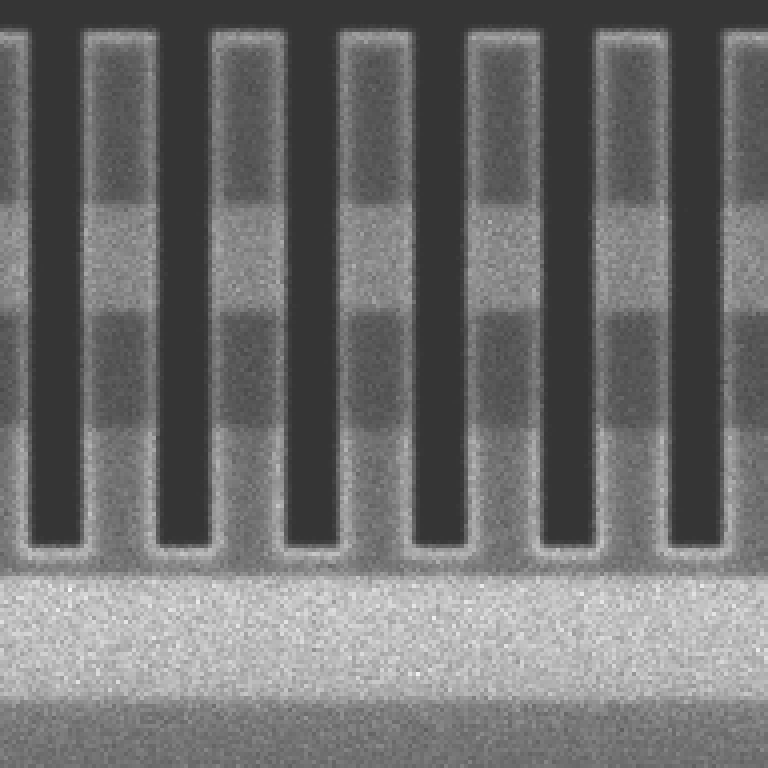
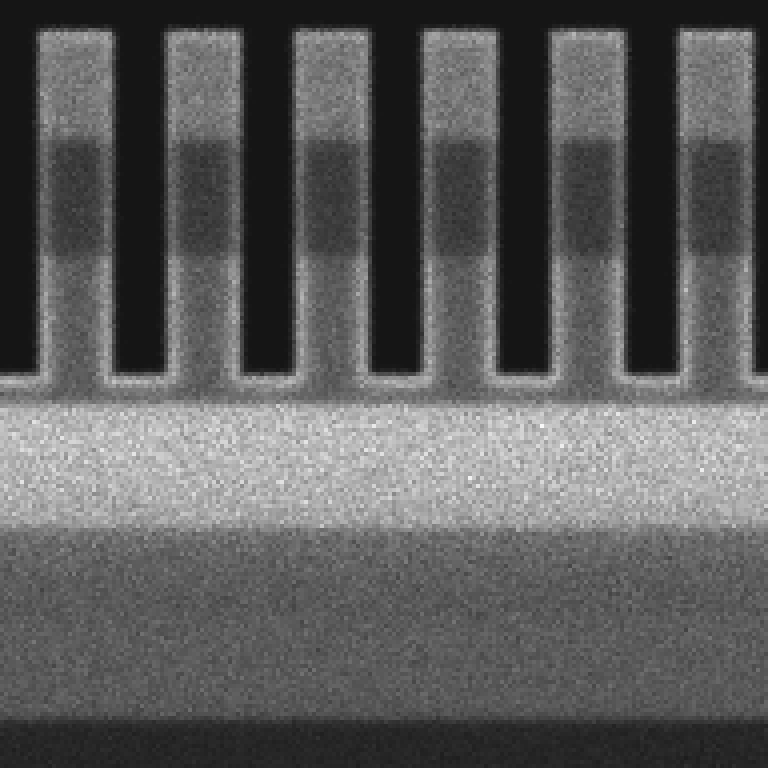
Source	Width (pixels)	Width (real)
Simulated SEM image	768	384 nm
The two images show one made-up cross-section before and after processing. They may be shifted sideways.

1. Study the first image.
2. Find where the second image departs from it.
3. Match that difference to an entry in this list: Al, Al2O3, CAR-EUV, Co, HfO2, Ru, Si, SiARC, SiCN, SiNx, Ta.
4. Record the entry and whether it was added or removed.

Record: SiARC / removed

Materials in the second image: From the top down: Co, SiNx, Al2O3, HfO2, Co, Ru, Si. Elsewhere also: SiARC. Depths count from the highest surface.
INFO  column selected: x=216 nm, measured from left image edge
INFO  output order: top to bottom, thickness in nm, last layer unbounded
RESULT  Co 54, SiNx 58, Al2O3 74, HfO2 62, Co 46, Ru 50, Si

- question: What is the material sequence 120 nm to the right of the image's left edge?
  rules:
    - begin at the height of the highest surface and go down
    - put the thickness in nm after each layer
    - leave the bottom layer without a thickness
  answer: empty 172, Al2O3 14, HfO2 62, Co 46, Ru 50, Si